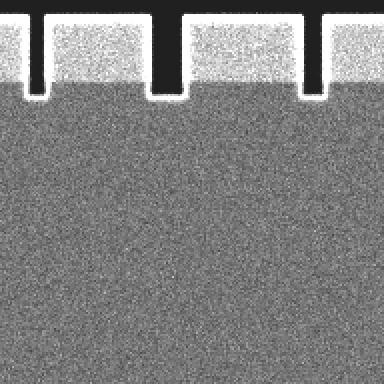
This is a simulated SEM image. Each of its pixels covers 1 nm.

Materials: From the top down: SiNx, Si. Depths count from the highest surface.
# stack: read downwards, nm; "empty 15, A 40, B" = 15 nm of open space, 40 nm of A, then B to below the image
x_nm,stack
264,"SiNx 66, Si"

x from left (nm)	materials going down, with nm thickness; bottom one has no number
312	empty 80, Si